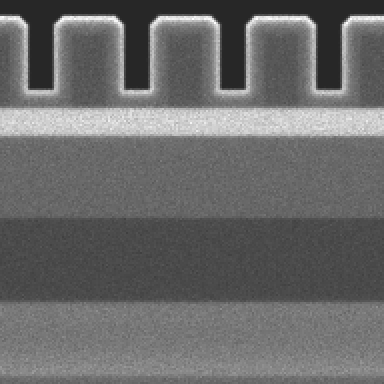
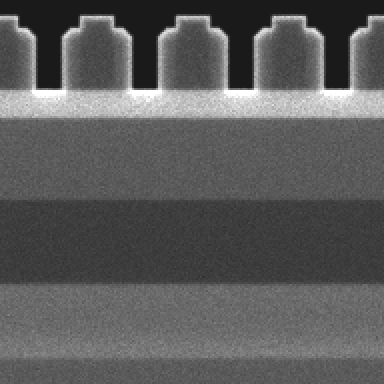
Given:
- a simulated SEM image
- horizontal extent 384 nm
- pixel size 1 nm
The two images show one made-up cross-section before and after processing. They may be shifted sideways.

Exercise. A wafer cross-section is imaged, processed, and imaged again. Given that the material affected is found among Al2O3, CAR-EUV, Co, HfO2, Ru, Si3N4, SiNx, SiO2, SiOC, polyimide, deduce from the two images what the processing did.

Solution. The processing removed SiO2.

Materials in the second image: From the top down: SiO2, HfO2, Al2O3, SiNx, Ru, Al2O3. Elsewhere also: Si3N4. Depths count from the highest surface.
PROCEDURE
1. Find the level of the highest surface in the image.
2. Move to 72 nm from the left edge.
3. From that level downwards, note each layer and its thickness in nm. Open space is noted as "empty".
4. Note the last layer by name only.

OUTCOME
empty 12, SiO2 62, HfO2 28, Al2O3 82, SiNx 84, Ru 74, Al2O3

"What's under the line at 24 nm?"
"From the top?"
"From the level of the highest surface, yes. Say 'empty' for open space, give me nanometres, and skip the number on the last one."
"empty 12, SiO2 62, HfO2 28, Al2O3 82, SiNx 84, Ru 74, Al2O3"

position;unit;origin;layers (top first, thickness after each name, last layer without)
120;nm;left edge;empty 12, SiO2 62, HfO2 28, Al2O3 82, SiNx 84, Ru 74, Al2O3